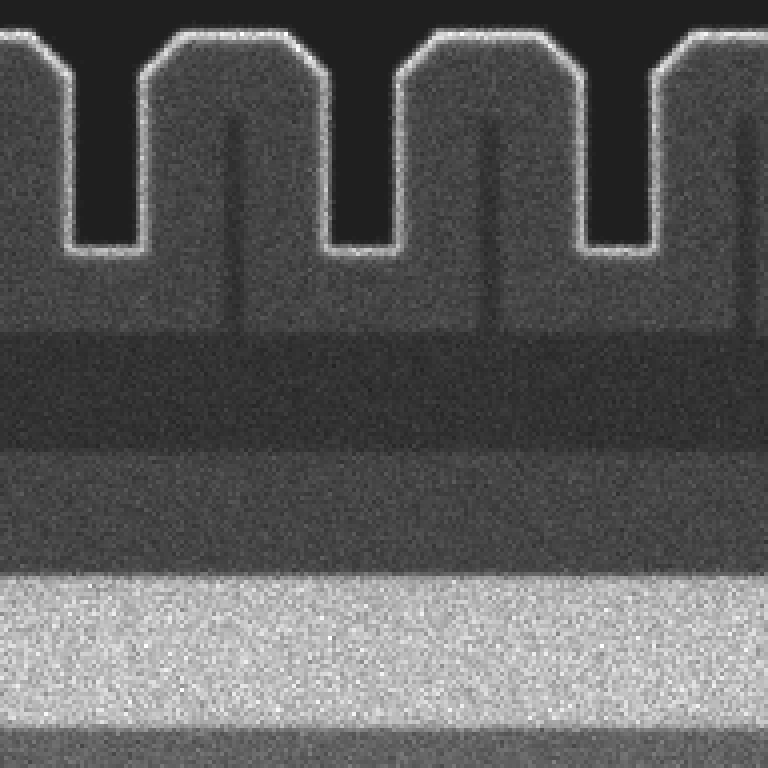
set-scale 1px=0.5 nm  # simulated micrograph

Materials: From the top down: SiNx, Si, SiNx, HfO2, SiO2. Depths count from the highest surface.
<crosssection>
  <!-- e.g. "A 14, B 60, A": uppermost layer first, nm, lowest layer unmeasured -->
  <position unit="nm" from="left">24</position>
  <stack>empty 10, SiNx 140, Si 60, SiNx 62, HfO2 76, SiO2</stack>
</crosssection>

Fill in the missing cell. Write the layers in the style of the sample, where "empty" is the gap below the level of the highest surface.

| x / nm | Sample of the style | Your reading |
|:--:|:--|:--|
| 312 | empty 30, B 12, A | empty 108, SiNx 42, Si 60, SiNx 62, HfO2 76, SiO2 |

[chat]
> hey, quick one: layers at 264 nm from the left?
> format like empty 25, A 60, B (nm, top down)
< SiNx 150, Si 60, SiNx 62, HfO2 76, SiO2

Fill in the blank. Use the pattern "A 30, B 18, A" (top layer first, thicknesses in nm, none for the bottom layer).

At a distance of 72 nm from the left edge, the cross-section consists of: empty 18, SiNx 132, Si 60, SiNx 62, HfO2 76, SiO2